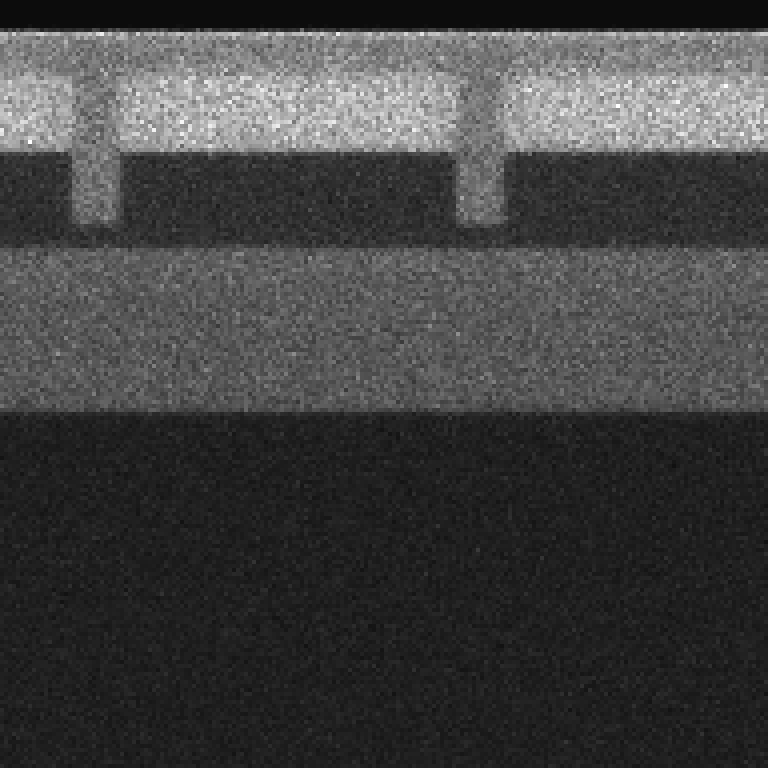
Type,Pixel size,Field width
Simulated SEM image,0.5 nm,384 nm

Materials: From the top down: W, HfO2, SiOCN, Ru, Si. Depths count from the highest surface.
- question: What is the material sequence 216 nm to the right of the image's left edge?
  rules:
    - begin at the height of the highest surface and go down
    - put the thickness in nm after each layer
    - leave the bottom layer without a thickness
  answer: W 22, HfO2 38, SiOCN 48, Ru 82, Si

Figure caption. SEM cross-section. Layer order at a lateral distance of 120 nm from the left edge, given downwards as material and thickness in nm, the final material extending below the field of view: W 22, HfO2 38, SiOCN 48, Ru 82, Si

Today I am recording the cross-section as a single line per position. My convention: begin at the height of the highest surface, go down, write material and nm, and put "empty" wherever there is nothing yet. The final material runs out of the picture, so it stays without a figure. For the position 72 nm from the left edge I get W 22, HfO2 38, SiOCN 48, Ru 82, Si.